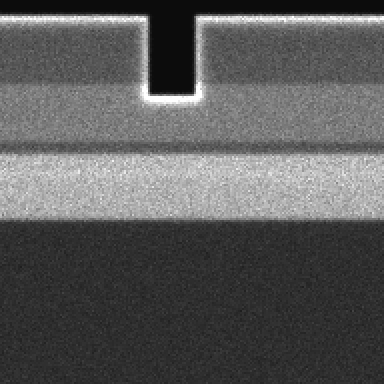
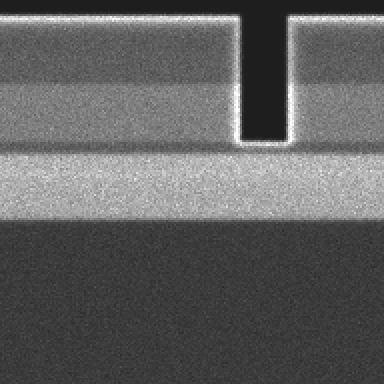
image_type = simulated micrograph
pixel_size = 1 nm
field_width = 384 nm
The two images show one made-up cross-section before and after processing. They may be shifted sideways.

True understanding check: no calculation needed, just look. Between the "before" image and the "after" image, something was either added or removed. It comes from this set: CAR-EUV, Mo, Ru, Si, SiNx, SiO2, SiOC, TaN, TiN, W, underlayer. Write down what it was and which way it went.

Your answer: SiO2 (removed)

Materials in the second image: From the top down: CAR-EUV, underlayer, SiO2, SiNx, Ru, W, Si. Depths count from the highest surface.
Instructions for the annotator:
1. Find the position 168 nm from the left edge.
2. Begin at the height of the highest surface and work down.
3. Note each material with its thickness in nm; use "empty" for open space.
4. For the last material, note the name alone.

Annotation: CAR-EUV 36, underlayer 32, SiO2 58, SiNx 12, Ru 16, W 50, Si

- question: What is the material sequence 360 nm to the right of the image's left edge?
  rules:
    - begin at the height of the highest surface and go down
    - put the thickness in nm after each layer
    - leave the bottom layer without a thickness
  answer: CAR-EUV 36, underlayer 32, SiO2 58, SiNx 12, Ru 16, W 50, Si